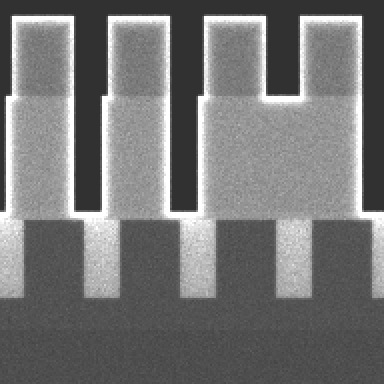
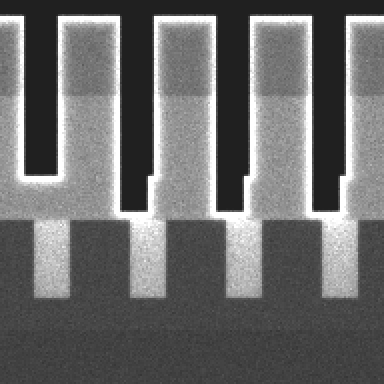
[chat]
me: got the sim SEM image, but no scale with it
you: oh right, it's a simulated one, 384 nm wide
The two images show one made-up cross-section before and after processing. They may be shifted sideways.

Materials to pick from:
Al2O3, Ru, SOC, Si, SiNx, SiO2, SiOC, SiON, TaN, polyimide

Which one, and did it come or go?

SiO2 - removed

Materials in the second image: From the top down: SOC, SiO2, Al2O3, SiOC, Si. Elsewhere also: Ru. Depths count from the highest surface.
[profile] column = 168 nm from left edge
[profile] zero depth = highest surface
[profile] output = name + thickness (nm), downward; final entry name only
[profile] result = SOC 80, SiO2 116, Al2O3 8, SiOC 110, Si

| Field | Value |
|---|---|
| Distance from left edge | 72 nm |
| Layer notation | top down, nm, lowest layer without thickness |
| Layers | SOC 80, SiO2 116, Al2O3 8, SiOC 110, Si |